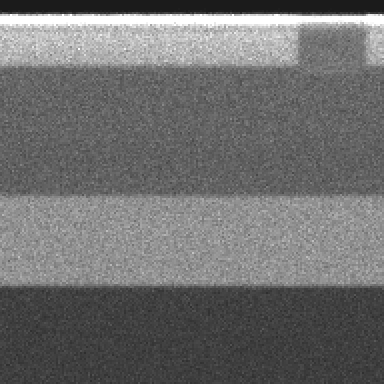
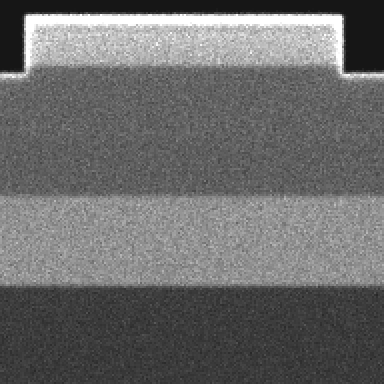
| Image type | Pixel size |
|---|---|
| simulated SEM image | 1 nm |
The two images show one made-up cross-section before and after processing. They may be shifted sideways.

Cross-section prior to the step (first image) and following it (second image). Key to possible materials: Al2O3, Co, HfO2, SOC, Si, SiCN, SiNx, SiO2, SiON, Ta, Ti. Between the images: SOC was removed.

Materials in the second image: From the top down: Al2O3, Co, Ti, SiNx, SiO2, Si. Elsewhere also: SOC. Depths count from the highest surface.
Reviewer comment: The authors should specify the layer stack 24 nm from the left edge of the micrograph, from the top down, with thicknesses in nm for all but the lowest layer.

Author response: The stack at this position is empty 58, Ti 68, SiNx 54, SiO2 90, Si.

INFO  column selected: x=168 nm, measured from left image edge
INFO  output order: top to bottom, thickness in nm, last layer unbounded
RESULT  Al2O3 16, Co 34, Ti 76, SiNx 54, SiO2 90, Si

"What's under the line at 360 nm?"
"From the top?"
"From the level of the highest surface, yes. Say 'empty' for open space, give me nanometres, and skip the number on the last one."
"empty 58, Ti 68, SiNx 54, SiO2 90, Si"